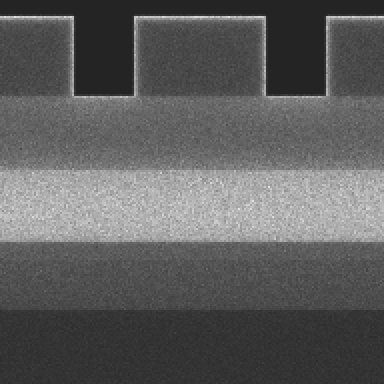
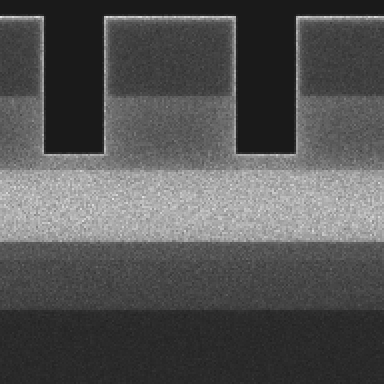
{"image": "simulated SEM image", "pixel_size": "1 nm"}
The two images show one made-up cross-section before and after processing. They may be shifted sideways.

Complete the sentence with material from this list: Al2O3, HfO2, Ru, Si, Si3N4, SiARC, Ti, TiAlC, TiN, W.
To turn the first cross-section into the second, Ru must be removed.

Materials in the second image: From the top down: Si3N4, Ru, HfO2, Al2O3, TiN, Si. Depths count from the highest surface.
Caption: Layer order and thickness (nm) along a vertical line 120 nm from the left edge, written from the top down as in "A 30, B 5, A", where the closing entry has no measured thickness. Si3N4 80, Ru 74, HfO2 72, Al2O3 18, TiN 50, Si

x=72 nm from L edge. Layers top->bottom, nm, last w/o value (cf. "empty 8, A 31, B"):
empty 138, Ru 16, HfO2 72, Al2O3 18, TiN 50, Si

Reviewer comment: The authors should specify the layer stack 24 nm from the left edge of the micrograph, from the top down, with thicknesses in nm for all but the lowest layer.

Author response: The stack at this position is Si3N4 80, Ru 74, HfO2 72, Al2O3 18, TiN 50, Si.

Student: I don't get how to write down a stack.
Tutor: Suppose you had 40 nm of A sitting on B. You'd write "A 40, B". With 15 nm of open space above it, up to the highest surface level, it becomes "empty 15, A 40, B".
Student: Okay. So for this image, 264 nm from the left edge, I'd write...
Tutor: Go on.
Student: empty 138, Ru 16, HfO2 72, Al2O3 18, TiN 50, Si